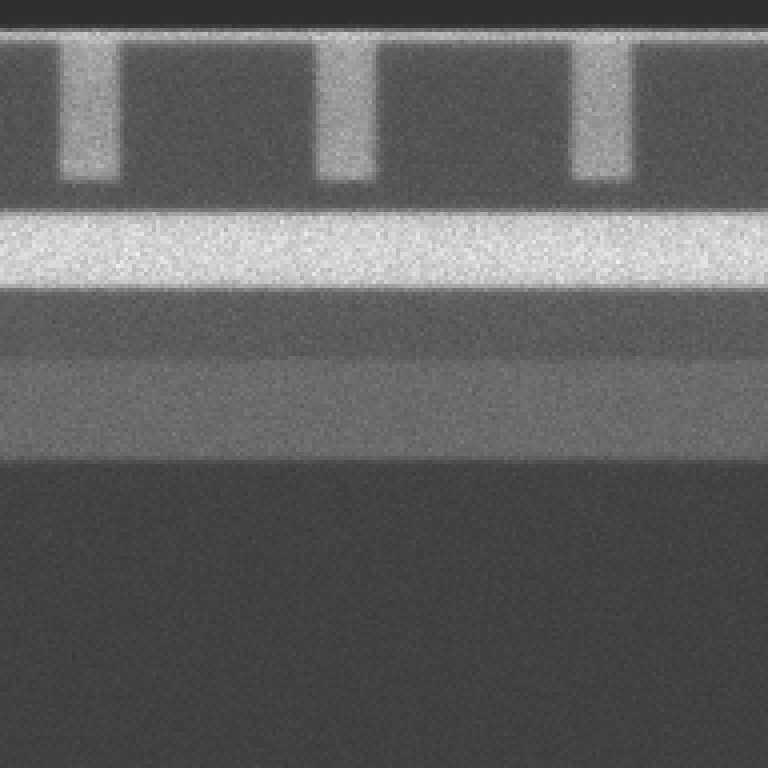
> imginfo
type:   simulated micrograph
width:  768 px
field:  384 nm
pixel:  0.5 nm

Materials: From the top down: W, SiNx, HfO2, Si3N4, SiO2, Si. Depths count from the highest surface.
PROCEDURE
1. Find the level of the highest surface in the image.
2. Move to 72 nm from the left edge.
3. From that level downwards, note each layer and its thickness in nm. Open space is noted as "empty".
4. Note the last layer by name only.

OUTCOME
SiNx 90, HfO2 38, Si3N4 36, SiO2 50, Si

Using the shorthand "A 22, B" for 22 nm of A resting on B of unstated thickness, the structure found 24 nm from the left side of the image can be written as SiNx 90, HfO2 38, Si3N4 36, SiO2 50, Si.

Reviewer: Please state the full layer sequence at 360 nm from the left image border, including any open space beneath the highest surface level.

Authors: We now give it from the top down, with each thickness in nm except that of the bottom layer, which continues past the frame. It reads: SiNx 90, HfO2 38, Si3N4 36, SiO2 50, Si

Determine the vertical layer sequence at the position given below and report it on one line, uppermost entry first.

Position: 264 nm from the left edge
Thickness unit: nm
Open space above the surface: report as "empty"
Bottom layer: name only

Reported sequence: SiNx 90, HfO2 38, Si3N4 36, SiO2 50, Si